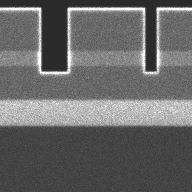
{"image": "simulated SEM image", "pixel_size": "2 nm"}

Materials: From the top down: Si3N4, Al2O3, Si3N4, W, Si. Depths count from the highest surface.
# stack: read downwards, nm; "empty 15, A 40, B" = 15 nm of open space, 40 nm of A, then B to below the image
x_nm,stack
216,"Si3N4 86, Al2O3 30, Si3N4 68, W 52, Si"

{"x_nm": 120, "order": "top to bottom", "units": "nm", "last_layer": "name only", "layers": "empty 128, Si3N4 56, W 52, Si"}